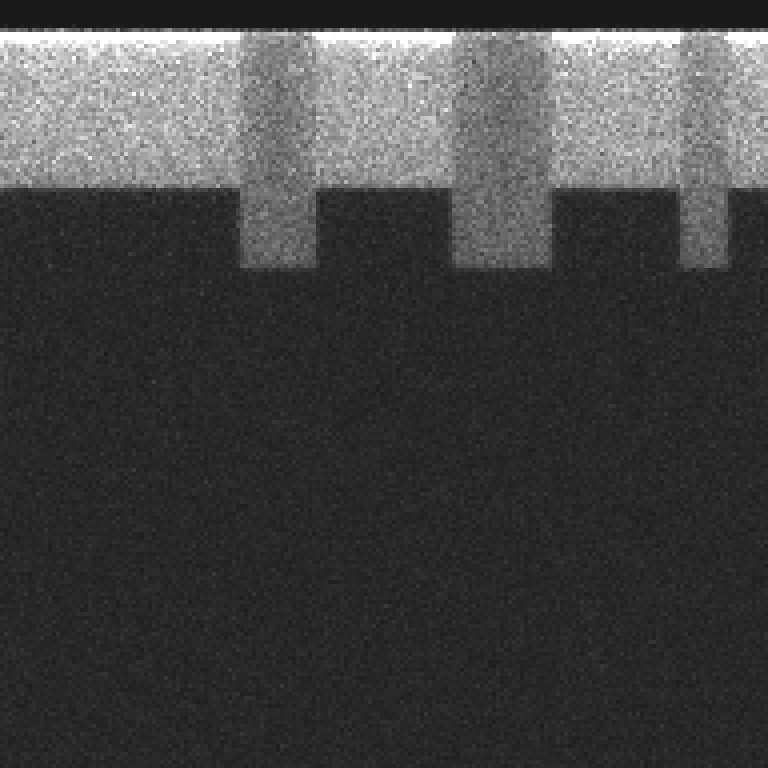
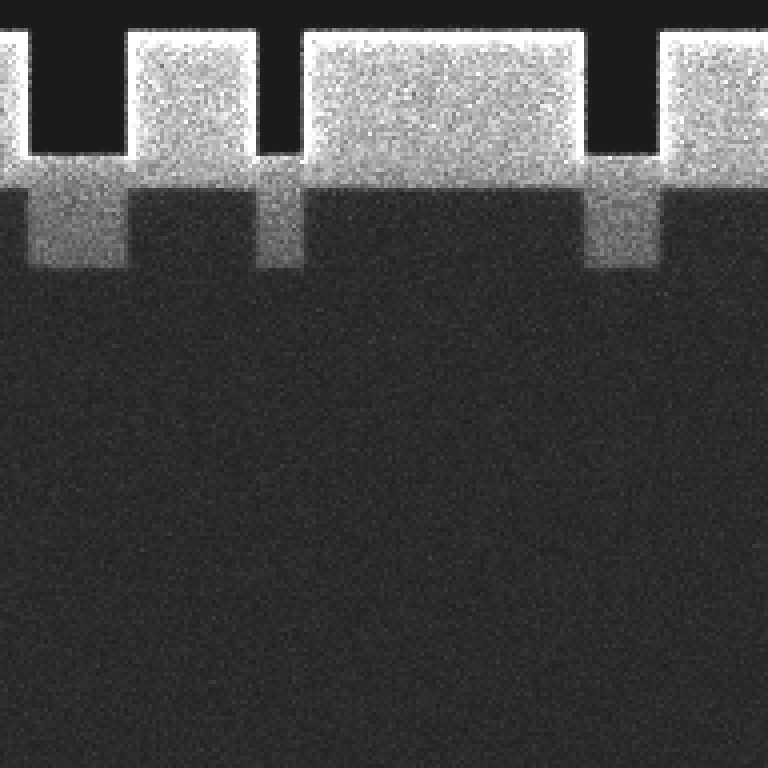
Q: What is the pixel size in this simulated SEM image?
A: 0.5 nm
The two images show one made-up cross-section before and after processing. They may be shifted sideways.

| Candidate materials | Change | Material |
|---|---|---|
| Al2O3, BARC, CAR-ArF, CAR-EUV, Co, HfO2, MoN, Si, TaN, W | removed | W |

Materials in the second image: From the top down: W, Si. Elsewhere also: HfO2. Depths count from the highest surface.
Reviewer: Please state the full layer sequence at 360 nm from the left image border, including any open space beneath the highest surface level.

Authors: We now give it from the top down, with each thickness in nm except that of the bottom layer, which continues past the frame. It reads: HfO2 78, Si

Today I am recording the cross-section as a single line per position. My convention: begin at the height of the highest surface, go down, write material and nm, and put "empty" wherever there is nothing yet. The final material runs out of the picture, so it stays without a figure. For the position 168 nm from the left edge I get HfO2 78, Si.